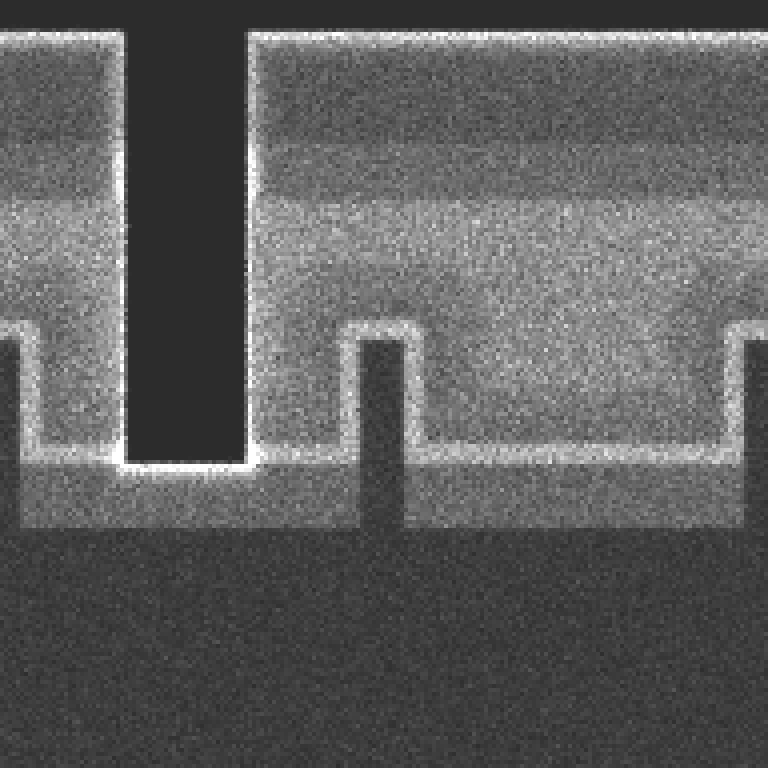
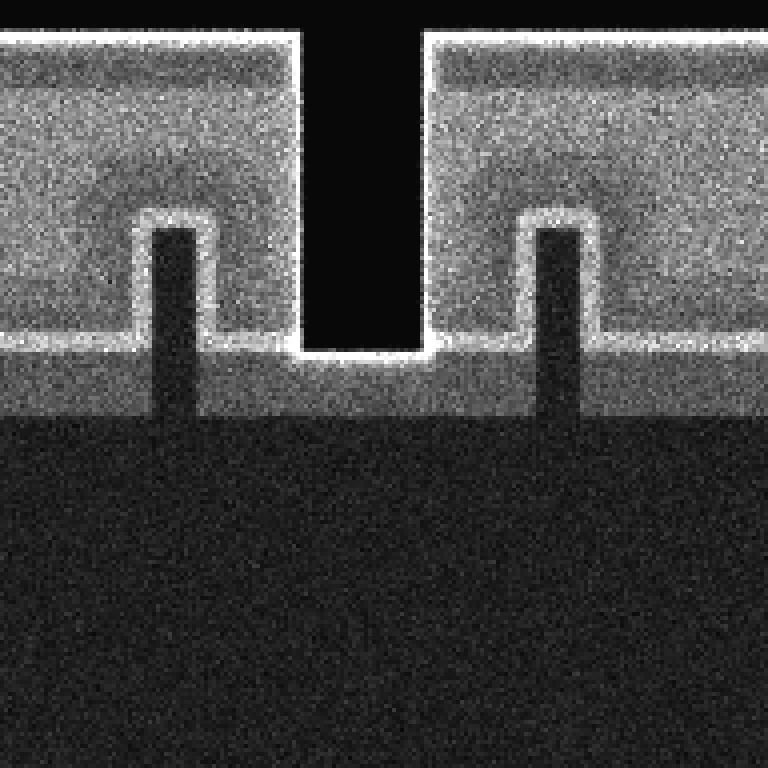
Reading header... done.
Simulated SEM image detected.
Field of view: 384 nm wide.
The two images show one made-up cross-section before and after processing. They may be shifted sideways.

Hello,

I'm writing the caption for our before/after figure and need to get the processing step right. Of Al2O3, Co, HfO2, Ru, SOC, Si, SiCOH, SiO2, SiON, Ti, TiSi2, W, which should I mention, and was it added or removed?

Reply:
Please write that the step removed SOC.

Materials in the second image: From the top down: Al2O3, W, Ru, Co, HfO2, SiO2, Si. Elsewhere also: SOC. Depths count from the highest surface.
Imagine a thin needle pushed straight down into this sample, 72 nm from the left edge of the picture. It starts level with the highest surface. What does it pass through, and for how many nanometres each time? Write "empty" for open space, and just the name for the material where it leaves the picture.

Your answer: Al2O3 28, W 32, Ru 16, Co 12, HfO2 72, SiO2 32, Si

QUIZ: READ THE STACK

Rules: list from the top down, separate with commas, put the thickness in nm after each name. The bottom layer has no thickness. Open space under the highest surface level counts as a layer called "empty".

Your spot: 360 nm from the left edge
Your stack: Al2O3 28, W 94, Ru 16, Co 12, HfO2 10, SiO2 32, Si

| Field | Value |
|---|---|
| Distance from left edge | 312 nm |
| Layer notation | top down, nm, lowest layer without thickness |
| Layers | Al2O3 28, W 36, Ru 74, Co 12, HfO2 10, SiO2 32, Si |